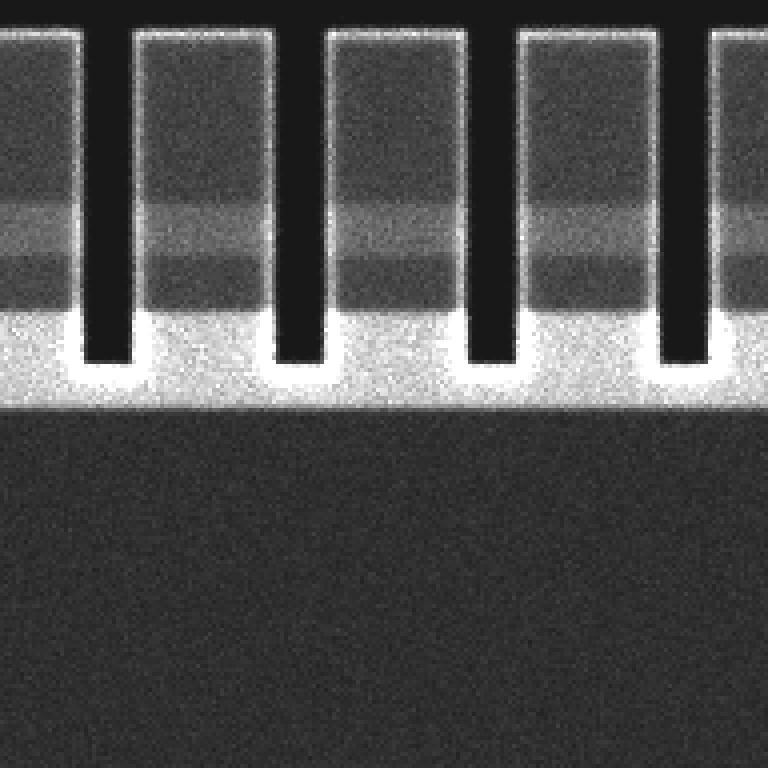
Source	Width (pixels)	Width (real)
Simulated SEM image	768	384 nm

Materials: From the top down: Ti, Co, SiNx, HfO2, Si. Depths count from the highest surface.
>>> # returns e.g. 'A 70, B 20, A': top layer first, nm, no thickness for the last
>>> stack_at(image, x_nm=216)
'Ti 86, Co 26, SiNx 28, HfO2 48, Si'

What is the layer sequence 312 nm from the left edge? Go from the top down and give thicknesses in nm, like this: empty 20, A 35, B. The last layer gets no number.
Ti 86, Co 26, SiNx 28, HfO2 48, Si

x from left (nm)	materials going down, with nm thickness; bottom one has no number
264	Ti 86, Co 26, SiNx 28, HfO2 48, Si